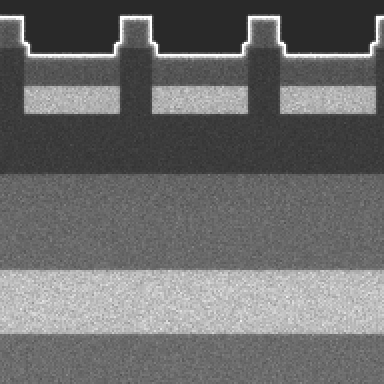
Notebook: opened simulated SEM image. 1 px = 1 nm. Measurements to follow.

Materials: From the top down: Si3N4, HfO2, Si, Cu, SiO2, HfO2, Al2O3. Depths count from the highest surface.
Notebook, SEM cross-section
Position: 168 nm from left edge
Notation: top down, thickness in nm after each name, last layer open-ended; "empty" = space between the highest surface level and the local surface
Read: empty 38, Si3N4 32, HfO2 28, Si 60, Cu 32, SiO2 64, HfO2 64, Al2O3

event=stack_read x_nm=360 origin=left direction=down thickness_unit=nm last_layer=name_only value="empty 38, Si3N4 32, HfO2 28, Si 60, Cu 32, SiO2 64, HfO2 64, Al2O3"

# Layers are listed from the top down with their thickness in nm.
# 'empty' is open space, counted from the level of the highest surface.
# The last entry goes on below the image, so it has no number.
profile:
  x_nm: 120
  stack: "Si3N4 32, Si 126, Cu 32, SiO2 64, HfO2 64, Al2O3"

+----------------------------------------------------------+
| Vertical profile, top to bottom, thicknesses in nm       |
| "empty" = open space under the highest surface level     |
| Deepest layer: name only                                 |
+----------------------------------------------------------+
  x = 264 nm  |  Si3N4 32, Si 126, Cu 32, SiO2 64, HfO2 64, Al2O3